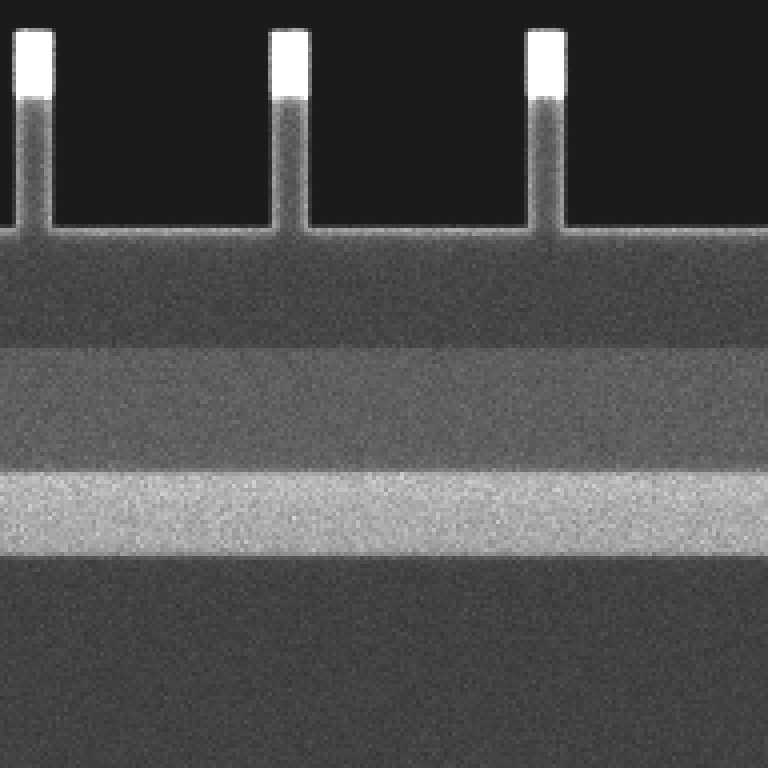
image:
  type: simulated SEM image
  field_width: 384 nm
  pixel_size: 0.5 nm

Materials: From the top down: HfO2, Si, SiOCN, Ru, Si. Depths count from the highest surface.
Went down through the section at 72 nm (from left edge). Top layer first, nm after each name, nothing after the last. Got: empty 98, Si 60, SiOCN 62, Ru 42, Si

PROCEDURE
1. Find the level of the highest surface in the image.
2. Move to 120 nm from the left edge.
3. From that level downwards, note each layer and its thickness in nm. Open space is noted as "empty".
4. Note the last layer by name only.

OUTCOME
empty 98, Si 60, SiOCN 62, Ru 42, Si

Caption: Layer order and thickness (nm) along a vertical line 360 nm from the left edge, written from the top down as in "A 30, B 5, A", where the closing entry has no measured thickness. empty 98, Si 60, SiOCN 62, Ru 42, Si